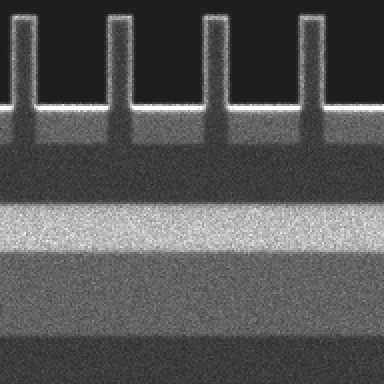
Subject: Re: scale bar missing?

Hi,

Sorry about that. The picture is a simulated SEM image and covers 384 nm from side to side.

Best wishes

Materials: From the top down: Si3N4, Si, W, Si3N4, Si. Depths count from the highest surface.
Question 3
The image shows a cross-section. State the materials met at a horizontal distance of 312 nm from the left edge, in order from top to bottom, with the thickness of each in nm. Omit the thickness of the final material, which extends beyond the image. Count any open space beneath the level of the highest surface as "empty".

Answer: Si 188, W 48, Si3N4 84, Si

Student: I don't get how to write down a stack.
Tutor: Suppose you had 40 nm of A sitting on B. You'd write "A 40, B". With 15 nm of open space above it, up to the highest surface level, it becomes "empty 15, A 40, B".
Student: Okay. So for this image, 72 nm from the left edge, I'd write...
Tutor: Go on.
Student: empty 90, Si3N4 38, Si 60, W 48, Si3N4 84, Si